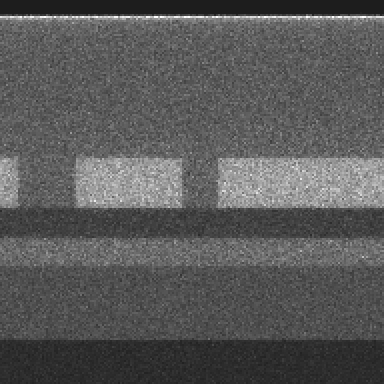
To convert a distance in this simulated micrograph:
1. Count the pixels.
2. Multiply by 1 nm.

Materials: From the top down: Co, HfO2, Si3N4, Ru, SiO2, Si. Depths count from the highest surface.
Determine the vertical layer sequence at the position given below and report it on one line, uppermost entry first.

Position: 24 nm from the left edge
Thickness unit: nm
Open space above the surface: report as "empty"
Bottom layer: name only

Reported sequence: Co 192, Si3N4 30, Ru 28, SiO2 74, Si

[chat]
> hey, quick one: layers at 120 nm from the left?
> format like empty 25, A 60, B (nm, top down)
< Co 142, HfO2 50, Si3N4 30, Ru 28, SiO2 74, Si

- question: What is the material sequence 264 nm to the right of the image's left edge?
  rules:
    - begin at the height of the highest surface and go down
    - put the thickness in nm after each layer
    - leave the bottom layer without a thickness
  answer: Co 142, HfO2 50, Si3N4 30, Ru 28, SiO2 74, Si